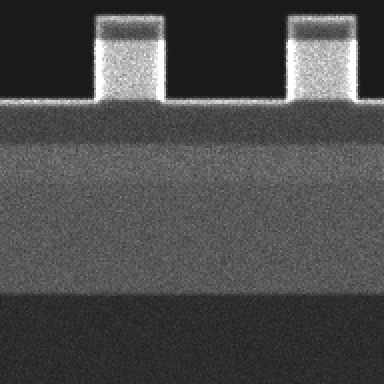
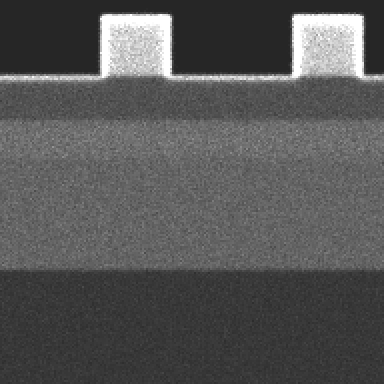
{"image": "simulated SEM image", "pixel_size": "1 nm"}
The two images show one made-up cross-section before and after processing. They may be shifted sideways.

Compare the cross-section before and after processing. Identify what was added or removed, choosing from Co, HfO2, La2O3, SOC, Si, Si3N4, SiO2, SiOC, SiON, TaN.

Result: SOC removed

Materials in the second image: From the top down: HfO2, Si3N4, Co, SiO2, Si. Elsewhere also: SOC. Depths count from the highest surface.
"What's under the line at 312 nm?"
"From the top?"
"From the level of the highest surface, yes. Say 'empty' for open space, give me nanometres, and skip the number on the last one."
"HfO2 60, Si3N4 44, Co 38, SiO2 112, Si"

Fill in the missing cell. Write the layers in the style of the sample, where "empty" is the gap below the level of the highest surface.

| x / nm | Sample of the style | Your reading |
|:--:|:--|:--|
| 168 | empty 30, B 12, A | HfO2 60, Si3N4 44, Co 38, SiO2 112, Si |